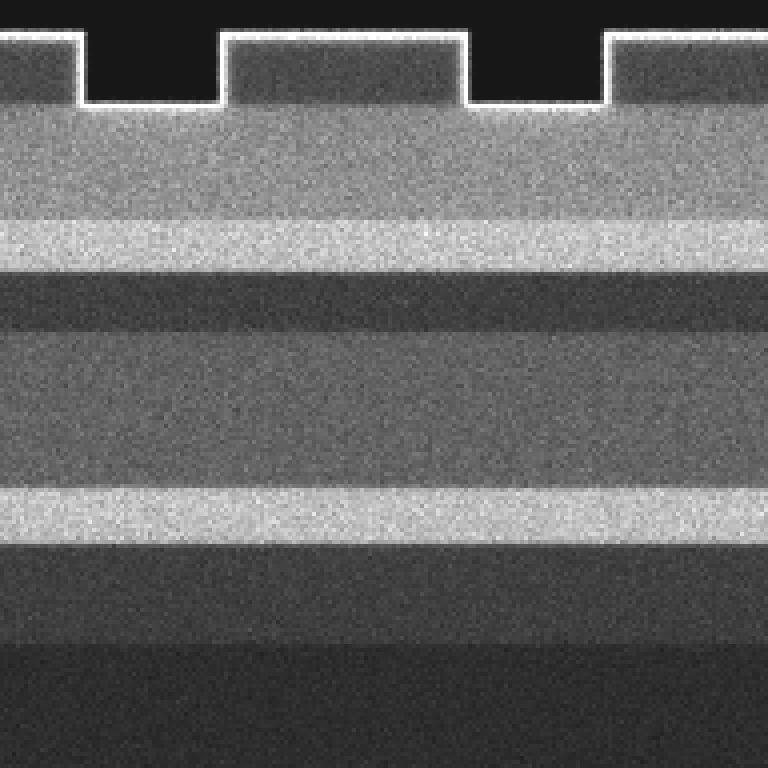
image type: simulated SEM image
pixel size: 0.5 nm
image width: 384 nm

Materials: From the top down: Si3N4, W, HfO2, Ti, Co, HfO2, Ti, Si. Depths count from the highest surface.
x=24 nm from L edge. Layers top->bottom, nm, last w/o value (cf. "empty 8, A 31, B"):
Si3N4 36, W 58, HfO2 26, Ti 30, Co 78, HfO2 28, Ti 50, Si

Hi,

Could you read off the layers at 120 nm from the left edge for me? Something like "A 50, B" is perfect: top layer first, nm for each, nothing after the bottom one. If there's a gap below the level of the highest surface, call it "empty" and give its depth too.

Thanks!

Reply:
Si3N4 36, W 58, HfO2 26, Ti 30, Co 78, HfO2 28, Ti 50, Si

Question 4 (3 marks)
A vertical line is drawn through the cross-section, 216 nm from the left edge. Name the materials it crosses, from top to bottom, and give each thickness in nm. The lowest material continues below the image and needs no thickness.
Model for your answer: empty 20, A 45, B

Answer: Si3N4 36, W 58, HfO2 26, Ti 30, Co 78, HfO2 28, Ti 50, Si